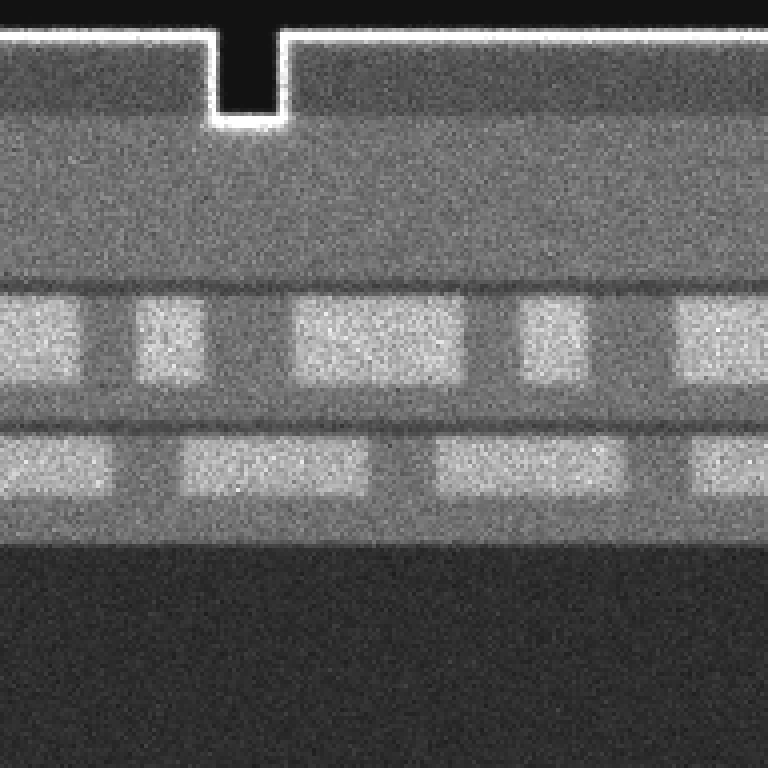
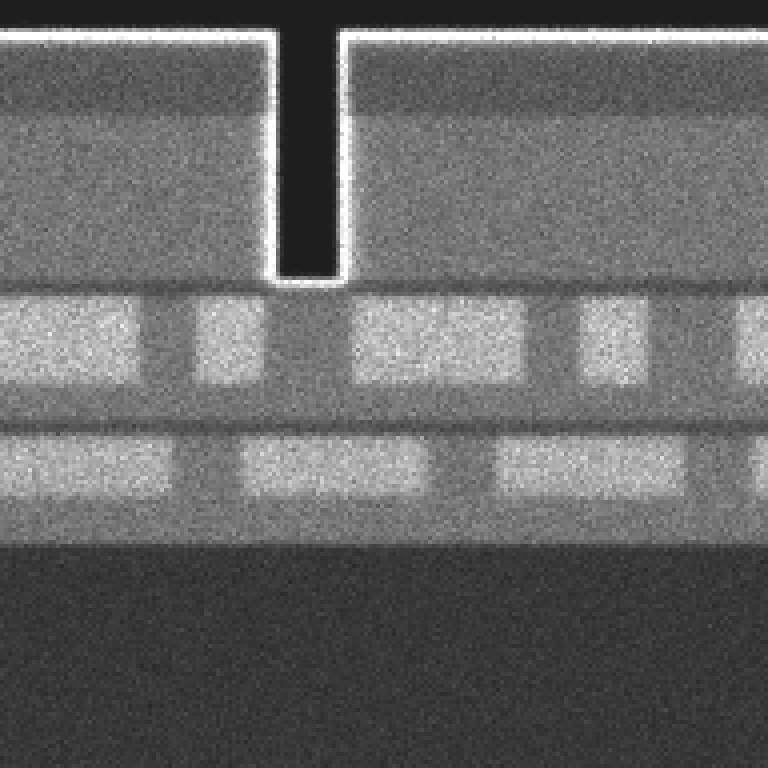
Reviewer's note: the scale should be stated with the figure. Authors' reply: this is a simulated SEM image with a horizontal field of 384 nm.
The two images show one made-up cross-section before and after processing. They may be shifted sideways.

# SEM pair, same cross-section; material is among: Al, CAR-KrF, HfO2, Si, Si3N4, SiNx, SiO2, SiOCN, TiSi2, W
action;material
removed;SiO2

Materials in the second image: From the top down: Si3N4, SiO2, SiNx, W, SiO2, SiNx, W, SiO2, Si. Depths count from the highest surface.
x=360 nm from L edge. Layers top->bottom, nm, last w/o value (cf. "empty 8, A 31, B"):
Si3N4 42, SiO2 82, SiNx 8, SiO2 62, SiNx 8, SiO2 54, Si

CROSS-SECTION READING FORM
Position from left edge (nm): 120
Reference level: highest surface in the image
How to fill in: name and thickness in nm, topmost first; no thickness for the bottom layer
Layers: Si3N4 42, SiO2 82, SiNx 8, W 44, SiO2 18, SiNx 8, W 30, SiO2 24, Si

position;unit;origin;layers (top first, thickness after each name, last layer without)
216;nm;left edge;Si3N4 42, SiO2 82, SiNx 8, W 44, SiO2 18, SiNx 8, SiO2 54, Si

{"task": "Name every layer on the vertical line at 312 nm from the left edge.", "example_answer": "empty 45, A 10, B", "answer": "Si3N4 42, SiO2 82, SiNx 8, W 44, SiO2 18, SiNx 8, W 30, SiO2 24, Si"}